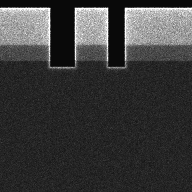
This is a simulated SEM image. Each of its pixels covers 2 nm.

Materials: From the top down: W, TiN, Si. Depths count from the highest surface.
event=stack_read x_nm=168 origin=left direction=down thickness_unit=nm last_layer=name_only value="W 74, TiN 32, Si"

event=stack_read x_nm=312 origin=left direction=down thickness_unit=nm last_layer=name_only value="W 74, TiN 32, Si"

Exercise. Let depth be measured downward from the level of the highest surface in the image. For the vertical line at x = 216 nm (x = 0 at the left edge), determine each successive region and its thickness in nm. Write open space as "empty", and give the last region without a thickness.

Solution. empty 118, Si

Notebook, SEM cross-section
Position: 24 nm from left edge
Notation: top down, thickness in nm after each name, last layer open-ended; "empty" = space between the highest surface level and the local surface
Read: W 74, TiN 32, Si